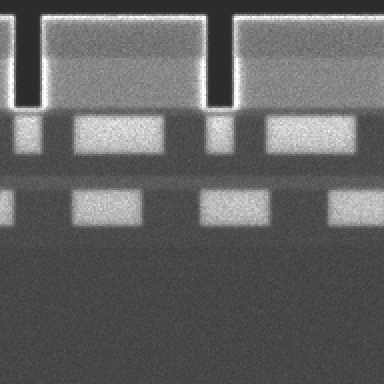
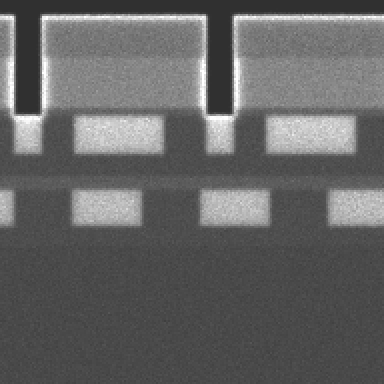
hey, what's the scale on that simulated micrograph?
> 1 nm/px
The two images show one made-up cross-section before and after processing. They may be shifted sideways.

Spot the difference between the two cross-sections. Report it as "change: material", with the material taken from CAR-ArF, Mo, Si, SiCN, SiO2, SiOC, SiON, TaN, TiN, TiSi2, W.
removed: SiCN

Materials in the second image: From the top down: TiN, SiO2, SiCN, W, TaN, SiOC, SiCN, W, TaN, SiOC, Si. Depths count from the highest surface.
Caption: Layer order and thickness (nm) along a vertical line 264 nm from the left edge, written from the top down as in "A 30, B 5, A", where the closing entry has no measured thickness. TiN 42, SiO2 50, SiCN 8, SiOC 60, SiCN 14, TaN 36, SiOC 20, Si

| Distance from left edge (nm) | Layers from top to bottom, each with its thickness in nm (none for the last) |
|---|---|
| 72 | TiN 42, SiO2 50, SiCN 8, SiOC 60, SiCN 14, TaN 36, SiOC 20, Si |